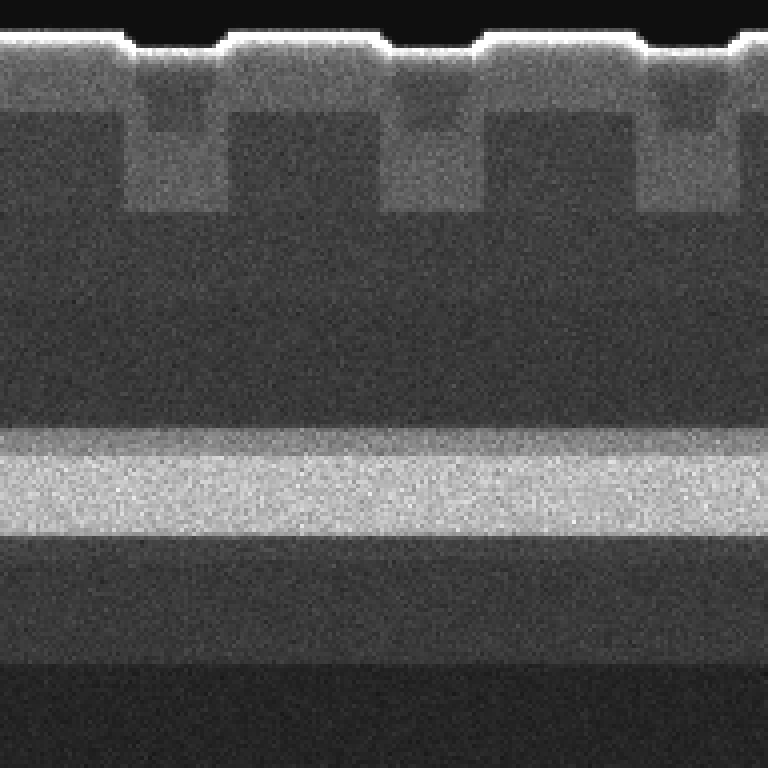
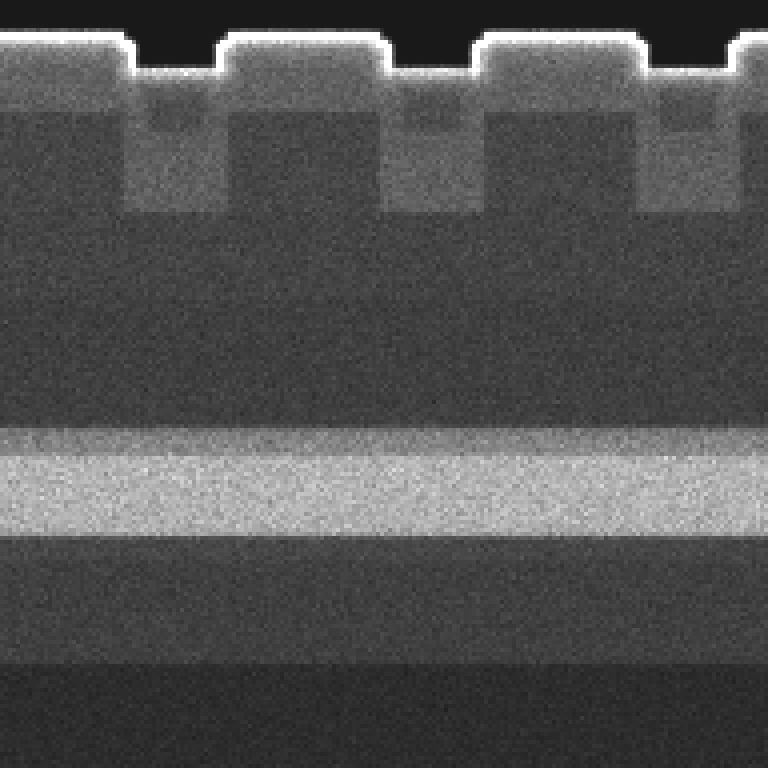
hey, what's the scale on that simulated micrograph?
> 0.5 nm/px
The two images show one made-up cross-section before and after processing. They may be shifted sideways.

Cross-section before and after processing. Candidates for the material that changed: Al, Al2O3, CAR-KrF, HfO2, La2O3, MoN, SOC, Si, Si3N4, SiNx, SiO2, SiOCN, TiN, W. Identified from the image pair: SOC (removed).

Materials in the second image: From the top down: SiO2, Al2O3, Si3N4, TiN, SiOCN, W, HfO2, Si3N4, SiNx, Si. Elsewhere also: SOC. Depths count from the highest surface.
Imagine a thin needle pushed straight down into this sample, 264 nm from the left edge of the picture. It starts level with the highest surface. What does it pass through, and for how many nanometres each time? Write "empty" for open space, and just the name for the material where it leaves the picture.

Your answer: SiO2 10, Al2O3 30, Si3N4 50, TiN 44, SiOCN 64, W 14, HfO2 40, Si3N4 12, SiNx 52, Si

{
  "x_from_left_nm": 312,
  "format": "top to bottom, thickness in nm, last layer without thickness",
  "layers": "SiO2 10, Al2O3 30, Si3N4 50, TiN 44, SiOCN 64, W 14, HfO2 40, Si3N4 12, SiNx 52, Si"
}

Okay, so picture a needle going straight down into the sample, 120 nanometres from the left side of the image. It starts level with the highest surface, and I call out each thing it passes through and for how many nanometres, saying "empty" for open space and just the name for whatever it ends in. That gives SiO2 10, Al2O3 30, Si3N4 50, TiN 44, SiOCN 64, W 14, HfO2 40, Si3N4 12, SiNx 52, Si